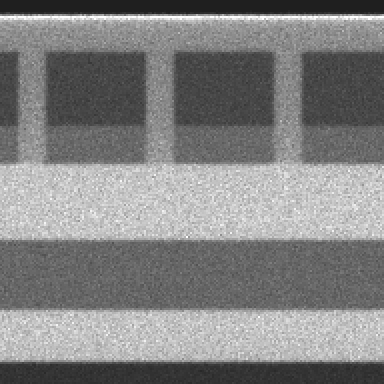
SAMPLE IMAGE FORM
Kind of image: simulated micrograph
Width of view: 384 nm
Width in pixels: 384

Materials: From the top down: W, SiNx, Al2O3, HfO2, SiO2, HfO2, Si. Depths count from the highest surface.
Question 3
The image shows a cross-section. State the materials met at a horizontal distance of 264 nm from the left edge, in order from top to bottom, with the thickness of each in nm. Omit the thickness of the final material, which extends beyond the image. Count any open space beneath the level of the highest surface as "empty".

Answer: W 36, SiNx 74, Al2O3 38, HfO2 76, SiO2 70, HfO2 52, Si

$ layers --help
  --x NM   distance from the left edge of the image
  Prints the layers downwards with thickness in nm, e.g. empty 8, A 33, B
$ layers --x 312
W 36, SiNx 74, Al2O3 38, HfO2 76, SiO2 70, HfO2 52, Si